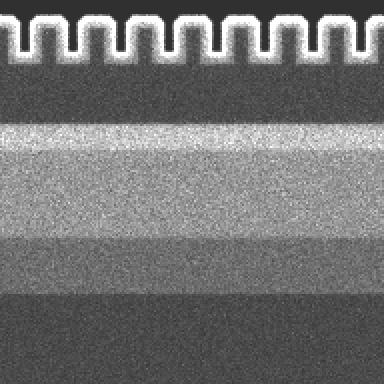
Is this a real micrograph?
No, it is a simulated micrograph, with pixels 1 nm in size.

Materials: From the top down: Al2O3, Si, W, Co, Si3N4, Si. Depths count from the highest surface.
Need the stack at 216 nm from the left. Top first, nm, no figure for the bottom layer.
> empty 36, Al2O3 12, Si 60, W 26, Co 88, Si3N4 56, Si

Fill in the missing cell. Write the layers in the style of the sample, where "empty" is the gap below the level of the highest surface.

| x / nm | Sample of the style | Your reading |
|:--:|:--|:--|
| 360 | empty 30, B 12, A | empty 36, Al2O3 12, Si 60, W 26, Co 88, Si3N4 56, Si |